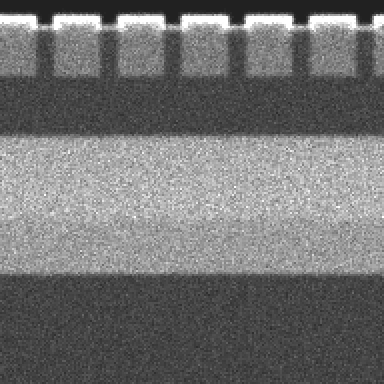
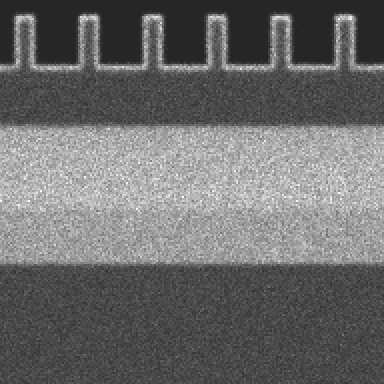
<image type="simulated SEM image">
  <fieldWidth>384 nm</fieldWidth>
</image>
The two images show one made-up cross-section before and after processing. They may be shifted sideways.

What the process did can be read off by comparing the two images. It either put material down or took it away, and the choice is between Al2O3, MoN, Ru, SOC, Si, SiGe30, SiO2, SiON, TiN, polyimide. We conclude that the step removed SOC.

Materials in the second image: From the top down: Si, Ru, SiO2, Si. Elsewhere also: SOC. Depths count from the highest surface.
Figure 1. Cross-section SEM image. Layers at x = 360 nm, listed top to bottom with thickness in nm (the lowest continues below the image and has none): empty 50, Si 60, Ru 84, SiO2 54, Si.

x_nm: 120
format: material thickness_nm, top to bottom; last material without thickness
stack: empty 50, Si 60, Ru 84, SiO2 54, Si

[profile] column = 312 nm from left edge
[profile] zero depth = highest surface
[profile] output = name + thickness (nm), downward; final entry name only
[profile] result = empty 50, Si 60, Ru 84, SiO2 54, Si